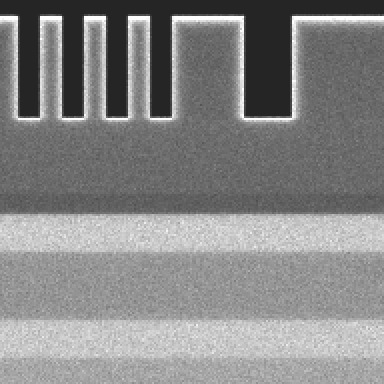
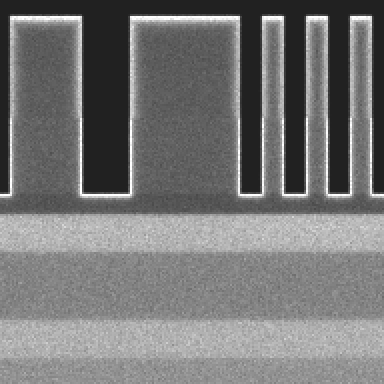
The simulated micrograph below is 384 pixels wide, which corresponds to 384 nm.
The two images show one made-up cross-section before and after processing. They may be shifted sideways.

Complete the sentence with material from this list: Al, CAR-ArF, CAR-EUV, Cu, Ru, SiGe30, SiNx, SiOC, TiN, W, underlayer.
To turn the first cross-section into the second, TiN must be removed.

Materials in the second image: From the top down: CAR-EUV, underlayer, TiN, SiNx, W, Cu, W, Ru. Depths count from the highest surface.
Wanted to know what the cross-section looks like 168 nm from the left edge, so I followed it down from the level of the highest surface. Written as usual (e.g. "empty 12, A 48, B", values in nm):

CAR-EUV 54, underlayer 48, TiN 76, SiNx 20, W 38, Cu 68, W 38, Ru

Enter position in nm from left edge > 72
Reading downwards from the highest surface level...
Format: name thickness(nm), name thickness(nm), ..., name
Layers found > CAR-EUV 54, underlayer 48, TiN 76, SiNx 20, W 38, Cu 68, W 38, Ru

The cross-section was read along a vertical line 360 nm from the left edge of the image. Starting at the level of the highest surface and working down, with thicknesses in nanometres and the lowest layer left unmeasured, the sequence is CAR-EUV 54, underlayer 48, TiN 76, SiNx 20, W 38, Cu 68, W 38, Ru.